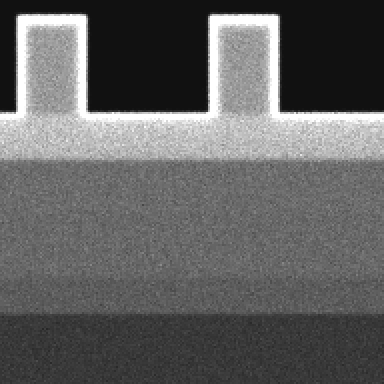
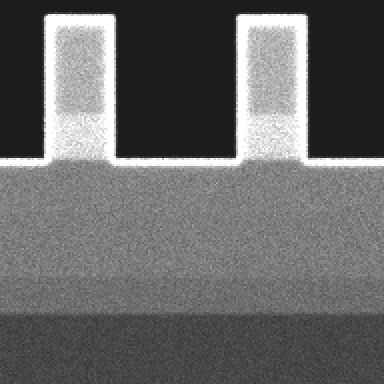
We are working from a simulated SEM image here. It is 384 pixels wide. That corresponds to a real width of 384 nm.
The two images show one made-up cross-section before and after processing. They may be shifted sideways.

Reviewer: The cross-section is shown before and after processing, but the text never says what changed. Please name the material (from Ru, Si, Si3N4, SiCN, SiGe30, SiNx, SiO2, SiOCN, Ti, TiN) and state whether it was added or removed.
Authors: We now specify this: Ru, removed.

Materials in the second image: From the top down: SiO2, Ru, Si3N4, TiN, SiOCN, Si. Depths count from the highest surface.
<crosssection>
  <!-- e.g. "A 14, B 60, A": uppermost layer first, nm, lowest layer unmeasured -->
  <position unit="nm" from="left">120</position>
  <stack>empty 144, Si3N4 52, TiN 66, SiOCN 36, Si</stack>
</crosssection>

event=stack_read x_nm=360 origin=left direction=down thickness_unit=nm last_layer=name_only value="empty 144, Si3N4 52, TiN 66, SiOCN 36, Si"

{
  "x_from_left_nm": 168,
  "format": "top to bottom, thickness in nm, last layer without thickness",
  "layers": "empty 144, Si3N4 52, TiN 66, SiOCN 36, Si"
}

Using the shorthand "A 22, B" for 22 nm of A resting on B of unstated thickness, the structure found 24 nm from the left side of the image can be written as empty 144, Si3N4 52, TiN 66, SiOCN 36, Si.